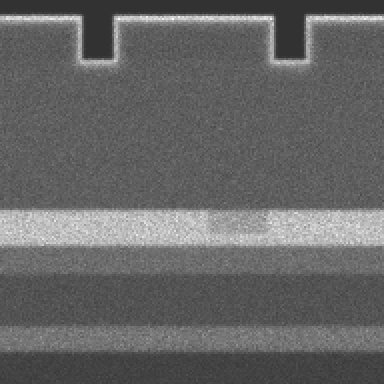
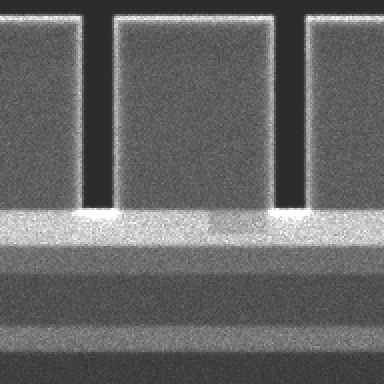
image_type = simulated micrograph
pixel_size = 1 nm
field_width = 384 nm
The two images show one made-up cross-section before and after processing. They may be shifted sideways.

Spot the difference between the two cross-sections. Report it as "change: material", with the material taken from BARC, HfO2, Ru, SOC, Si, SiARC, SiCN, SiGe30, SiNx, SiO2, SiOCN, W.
removed: SOC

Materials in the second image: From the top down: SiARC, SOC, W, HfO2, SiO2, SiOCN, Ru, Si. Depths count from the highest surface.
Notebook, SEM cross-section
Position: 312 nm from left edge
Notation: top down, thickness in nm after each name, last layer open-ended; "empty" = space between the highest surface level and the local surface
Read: SiARC 44, SOC 150, HfO2 36, SiO2 28, SiOCN 52, Ru 26, Si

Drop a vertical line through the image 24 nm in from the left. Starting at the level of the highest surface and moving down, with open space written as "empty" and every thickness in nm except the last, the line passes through SiARC 44, SOC 150, HfO2 36, SiO2 28, SiOCN 52, Ru 26, Si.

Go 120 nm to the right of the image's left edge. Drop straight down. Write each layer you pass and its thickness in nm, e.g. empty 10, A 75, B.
SiARC 44, SOC 150, HfO2 36, SiO2 28, SiOCN 52, Ru 26, Si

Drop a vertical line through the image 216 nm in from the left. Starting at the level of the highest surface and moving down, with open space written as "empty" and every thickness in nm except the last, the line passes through SiARC 44, SOC 150, W 24, HfO2 12, SiO2 28, SiOCN 52, Ru 26, Si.